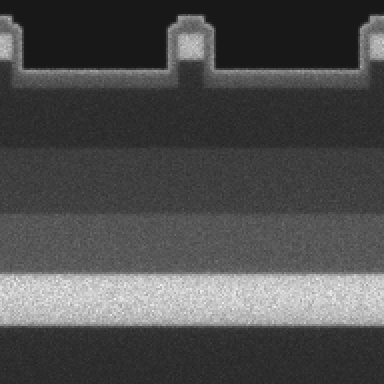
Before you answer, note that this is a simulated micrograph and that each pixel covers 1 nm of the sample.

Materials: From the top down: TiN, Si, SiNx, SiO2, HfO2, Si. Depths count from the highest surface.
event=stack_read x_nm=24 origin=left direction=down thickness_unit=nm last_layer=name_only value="empty 54, TiN 18, Si 60, SiNx 66, SiO2 60, HfO2 52, Si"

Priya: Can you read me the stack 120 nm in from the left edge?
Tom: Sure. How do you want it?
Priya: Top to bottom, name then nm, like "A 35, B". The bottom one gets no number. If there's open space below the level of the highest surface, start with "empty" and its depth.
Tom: empty 54, TiN 18, Si 60, SiNx 66, SiO2 60, HfO2 52, Si